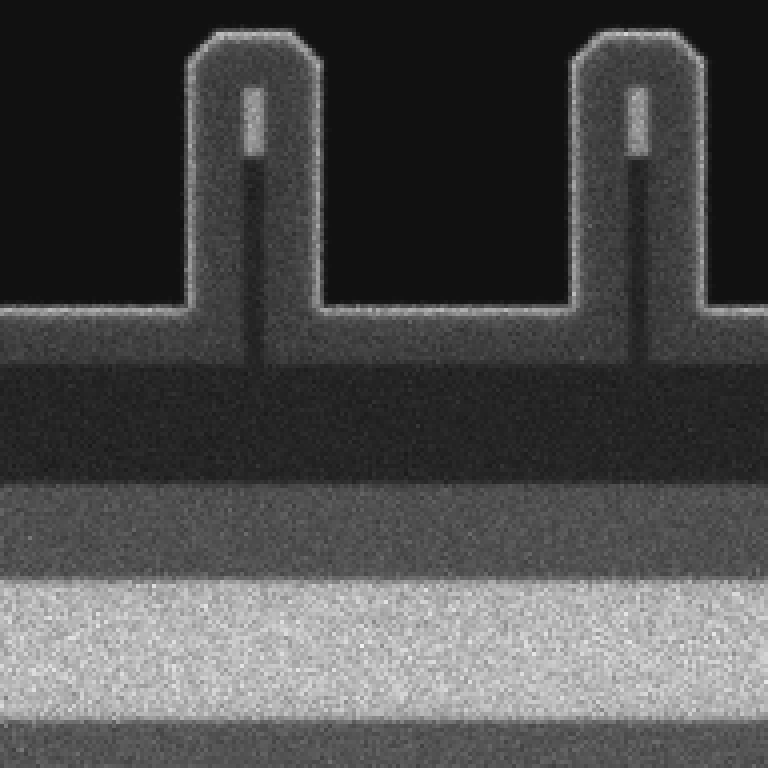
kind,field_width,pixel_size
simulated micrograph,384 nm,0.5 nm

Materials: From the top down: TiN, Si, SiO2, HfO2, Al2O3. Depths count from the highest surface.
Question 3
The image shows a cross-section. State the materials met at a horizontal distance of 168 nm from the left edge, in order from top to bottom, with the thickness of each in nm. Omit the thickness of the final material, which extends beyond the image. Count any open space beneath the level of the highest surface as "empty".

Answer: empty 138, TiN 28, Si 60, SiO2 48, HfO2 70, Al2O3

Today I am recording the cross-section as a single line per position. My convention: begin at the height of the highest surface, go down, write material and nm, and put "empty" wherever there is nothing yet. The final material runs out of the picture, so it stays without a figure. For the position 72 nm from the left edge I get empty 138, TiN 28, Si 60, SiO2 48, HfO2 70, Al2O3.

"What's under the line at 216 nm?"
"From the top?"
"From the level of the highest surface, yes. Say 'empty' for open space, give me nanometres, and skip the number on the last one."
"empty 138, TiN 28, Si 60, SiO2 48, HfO2 70, Al2O3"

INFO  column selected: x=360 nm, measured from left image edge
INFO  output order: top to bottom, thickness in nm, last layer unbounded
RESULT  empty 138, TiN 28, Si 60, SiO2 48, HfO2 70, Al2O3